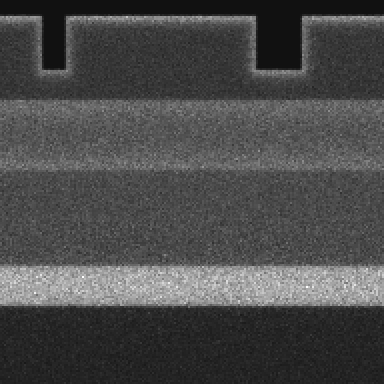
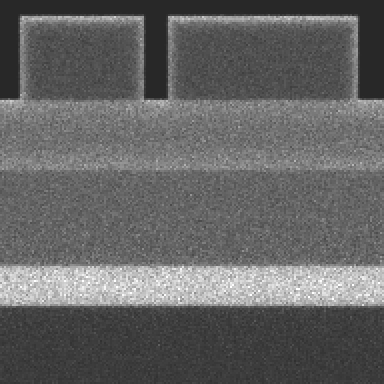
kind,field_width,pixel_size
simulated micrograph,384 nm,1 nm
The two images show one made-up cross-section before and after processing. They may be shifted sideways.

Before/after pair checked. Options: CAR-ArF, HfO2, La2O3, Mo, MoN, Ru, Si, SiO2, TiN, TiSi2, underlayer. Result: removed underlayer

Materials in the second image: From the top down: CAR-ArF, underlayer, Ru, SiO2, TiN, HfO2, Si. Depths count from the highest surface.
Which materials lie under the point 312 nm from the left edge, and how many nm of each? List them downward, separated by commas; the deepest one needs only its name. CAR-ArF 54, underlayer 30, Ru 70, SiO2 50, TiN 46, HfO2 40, Si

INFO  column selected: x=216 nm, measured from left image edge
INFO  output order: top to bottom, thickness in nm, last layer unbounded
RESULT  CAR-ArF 54, underlayer 30, Ru 70, SiO2 50, TiN 46, HfO2 40, Si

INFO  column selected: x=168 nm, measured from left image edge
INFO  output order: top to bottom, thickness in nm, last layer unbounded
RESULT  CAR-ArF 54, underlayer 30, Ru 70, SiO2 50, TiN 46, HfO2 40, Si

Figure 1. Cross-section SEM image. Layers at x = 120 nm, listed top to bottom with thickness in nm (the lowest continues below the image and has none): CAR-ArF 54, underlayer 30, Ru 70, SiO2 50, TiN 46, HfO2 40, Si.